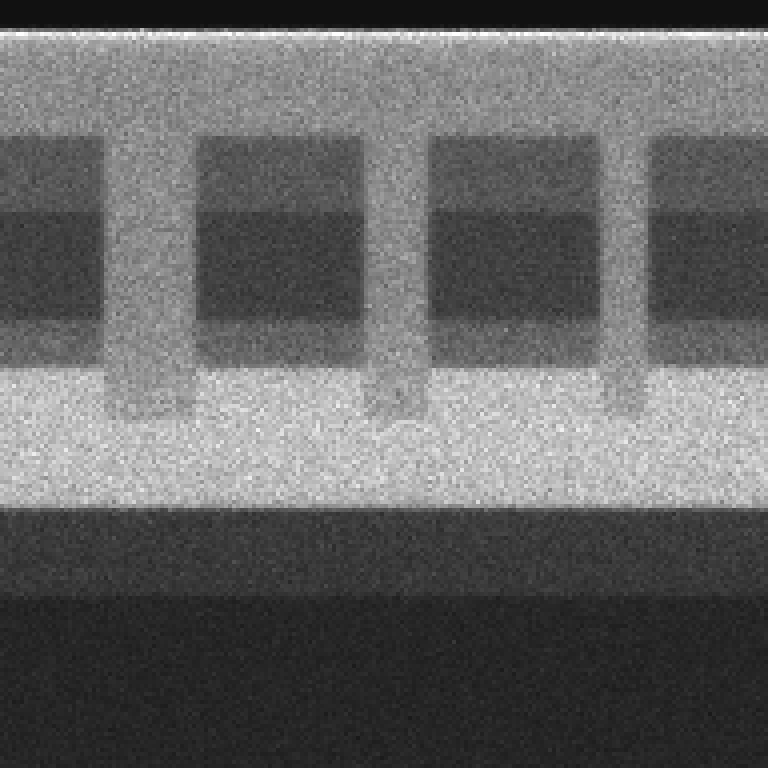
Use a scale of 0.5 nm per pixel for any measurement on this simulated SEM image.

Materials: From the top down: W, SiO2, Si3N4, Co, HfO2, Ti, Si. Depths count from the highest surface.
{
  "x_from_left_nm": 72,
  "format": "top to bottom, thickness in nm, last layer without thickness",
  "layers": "W 194, HfO2 44, Ti 44, Si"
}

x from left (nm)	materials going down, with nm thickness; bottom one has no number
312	W 194, HfO2 44, Ti 44, Si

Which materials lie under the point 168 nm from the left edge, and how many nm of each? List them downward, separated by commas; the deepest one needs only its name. W 52, SiO2 38, Si3N4 54, Co 24, HfO2 70, Ti 44, Si